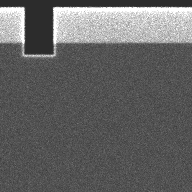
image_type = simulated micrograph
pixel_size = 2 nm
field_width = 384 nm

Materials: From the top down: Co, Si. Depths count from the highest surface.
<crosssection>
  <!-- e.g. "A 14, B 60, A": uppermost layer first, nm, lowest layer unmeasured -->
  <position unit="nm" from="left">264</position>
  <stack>Co 70, Si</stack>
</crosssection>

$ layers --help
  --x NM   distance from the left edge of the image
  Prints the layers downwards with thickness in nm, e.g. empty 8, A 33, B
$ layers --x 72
empty 94, Si